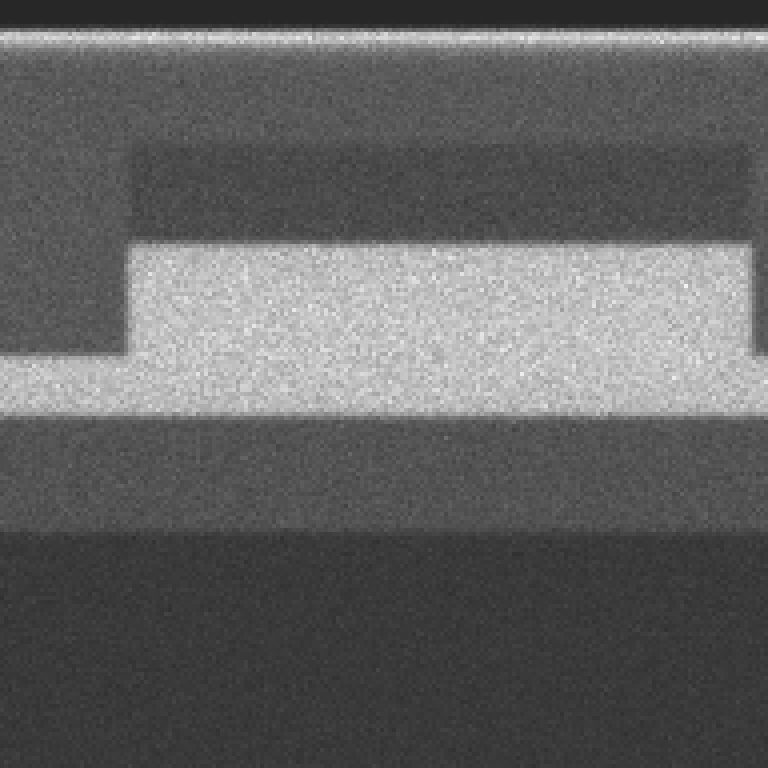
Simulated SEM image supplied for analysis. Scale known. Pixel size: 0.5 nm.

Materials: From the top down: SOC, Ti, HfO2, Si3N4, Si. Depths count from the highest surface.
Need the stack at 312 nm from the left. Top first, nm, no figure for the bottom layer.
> SOC 56, Ti 50, HfO2 86, Si3N4 58, Si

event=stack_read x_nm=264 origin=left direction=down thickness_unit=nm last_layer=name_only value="SOC 56, Ti 50, HfO2 86, Si3N4 58, Si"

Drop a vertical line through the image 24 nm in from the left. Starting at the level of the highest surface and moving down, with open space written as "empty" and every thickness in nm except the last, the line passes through SOC 162, HfO2 30, Si3N4 58, Si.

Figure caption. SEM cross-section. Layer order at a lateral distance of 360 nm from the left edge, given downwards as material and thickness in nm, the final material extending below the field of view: SOC 56, Ti 50, HfO2 86, Si3N4 58, Si